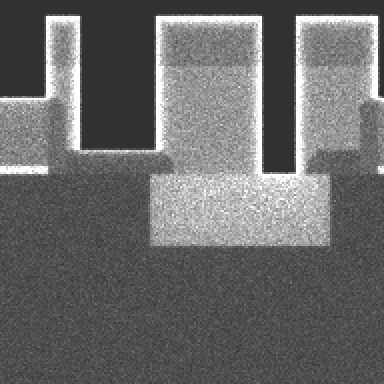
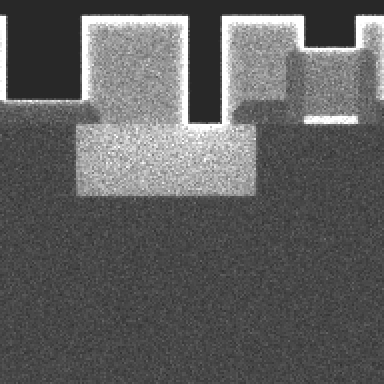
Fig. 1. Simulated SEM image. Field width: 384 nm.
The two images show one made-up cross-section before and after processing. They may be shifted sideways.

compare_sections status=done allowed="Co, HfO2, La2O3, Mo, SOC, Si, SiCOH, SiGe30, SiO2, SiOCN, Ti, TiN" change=removed material="SOC"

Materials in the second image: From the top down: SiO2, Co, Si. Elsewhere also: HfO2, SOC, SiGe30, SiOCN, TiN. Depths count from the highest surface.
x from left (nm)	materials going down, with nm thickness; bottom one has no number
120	SiO2 108, Co 72, Si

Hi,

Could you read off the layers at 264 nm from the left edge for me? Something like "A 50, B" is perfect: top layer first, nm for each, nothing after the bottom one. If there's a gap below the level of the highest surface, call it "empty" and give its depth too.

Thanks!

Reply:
SiO2 84, SiGe30 24, Si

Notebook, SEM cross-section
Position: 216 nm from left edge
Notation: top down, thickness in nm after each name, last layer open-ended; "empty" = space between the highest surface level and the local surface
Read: empty 108, Co 72, Si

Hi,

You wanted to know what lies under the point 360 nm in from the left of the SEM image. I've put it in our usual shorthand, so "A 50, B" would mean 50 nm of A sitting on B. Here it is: SiO2 32, SiOCN 76, Si